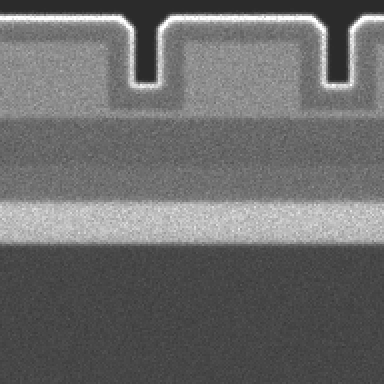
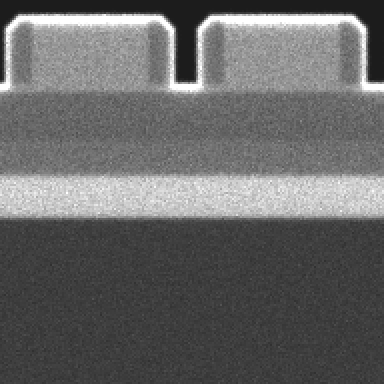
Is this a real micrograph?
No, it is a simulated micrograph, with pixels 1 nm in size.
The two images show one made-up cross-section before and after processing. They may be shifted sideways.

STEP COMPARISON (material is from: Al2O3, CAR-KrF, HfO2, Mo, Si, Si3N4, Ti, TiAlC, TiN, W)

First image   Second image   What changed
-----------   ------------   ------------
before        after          Si3N4, removed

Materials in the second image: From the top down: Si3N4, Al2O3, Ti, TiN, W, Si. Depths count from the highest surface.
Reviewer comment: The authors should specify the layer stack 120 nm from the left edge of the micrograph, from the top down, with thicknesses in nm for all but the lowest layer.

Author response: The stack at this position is Al2O3 76, Ti 48, TiN 36, W 42, Si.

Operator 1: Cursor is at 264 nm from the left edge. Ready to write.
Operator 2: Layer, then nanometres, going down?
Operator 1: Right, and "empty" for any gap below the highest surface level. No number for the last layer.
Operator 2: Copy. Al2O3 76, Ti 48, TiN 36, W 42, Si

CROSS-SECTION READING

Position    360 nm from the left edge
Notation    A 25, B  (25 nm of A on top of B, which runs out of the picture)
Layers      empty 8, Si3N4 60, Al2O3 8, Ti 48, TiN 36, W 42, Si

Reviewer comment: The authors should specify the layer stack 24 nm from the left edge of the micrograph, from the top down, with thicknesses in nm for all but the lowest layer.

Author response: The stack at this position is Si3N4 68, Al2O3 8, Ti 48, TiN 36, W 42, Si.